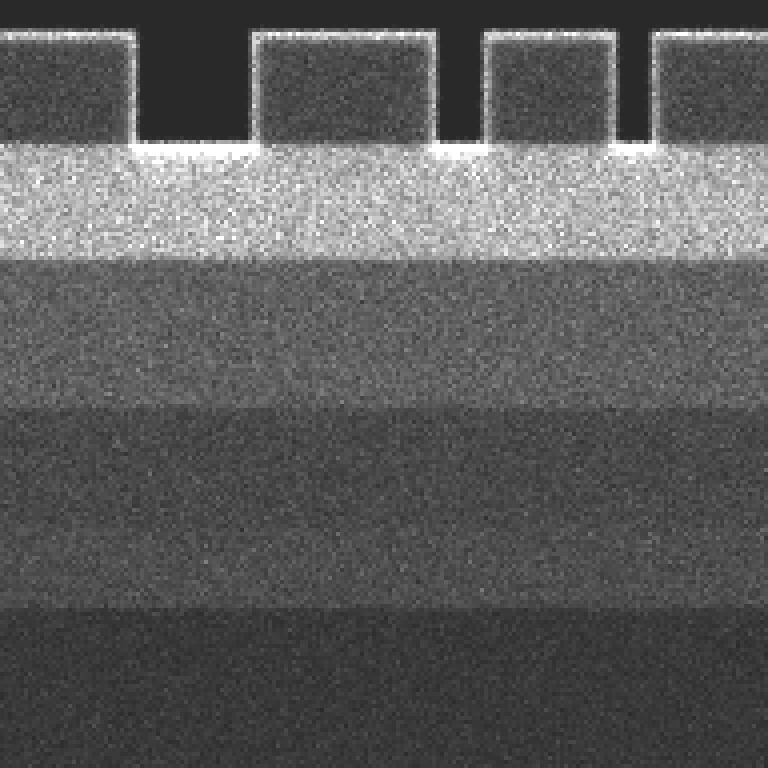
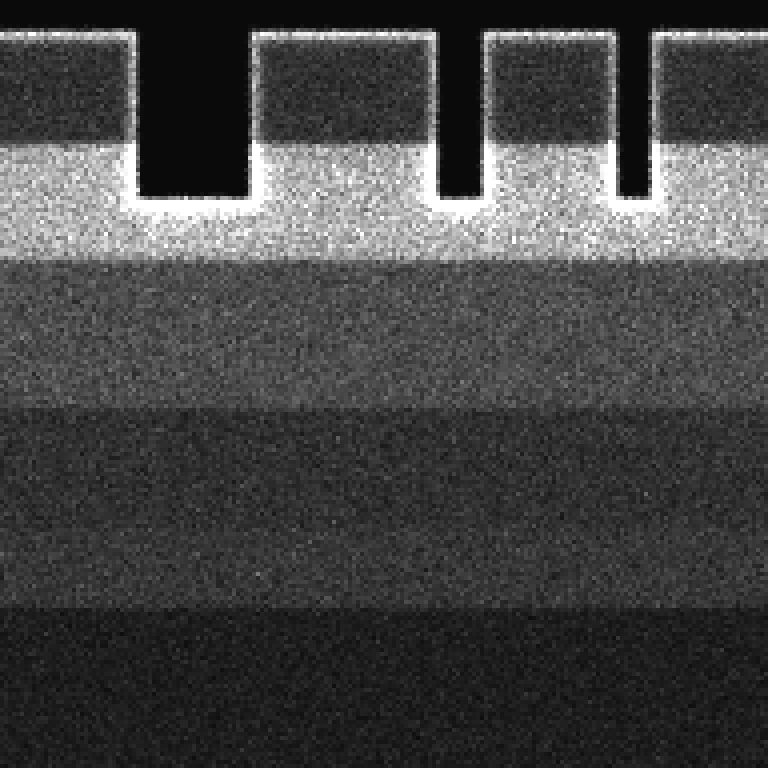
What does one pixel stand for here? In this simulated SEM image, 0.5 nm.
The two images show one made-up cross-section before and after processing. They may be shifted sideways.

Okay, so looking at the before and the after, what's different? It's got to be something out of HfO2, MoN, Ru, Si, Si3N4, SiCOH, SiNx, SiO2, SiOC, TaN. HfO2, removed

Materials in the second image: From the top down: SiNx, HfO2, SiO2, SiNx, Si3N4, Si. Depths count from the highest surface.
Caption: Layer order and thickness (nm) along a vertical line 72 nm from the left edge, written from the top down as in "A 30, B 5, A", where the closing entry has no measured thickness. empty 84, HfO2 30, SiO2 74, SiNx 60, Si3N4 40, Si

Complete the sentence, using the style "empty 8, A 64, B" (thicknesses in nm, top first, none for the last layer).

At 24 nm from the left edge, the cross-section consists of SiNx 56, HfO2 58, SiO2 74, SiNx 60, Si3N4 40, Si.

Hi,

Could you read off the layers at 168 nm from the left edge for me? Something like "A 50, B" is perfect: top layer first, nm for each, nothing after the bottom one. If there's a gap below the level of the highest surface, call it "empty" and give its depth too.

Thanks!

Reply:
SiNx 56, HfO2 58, SiO2 74, SiNx 60, Si3N4 40, Si